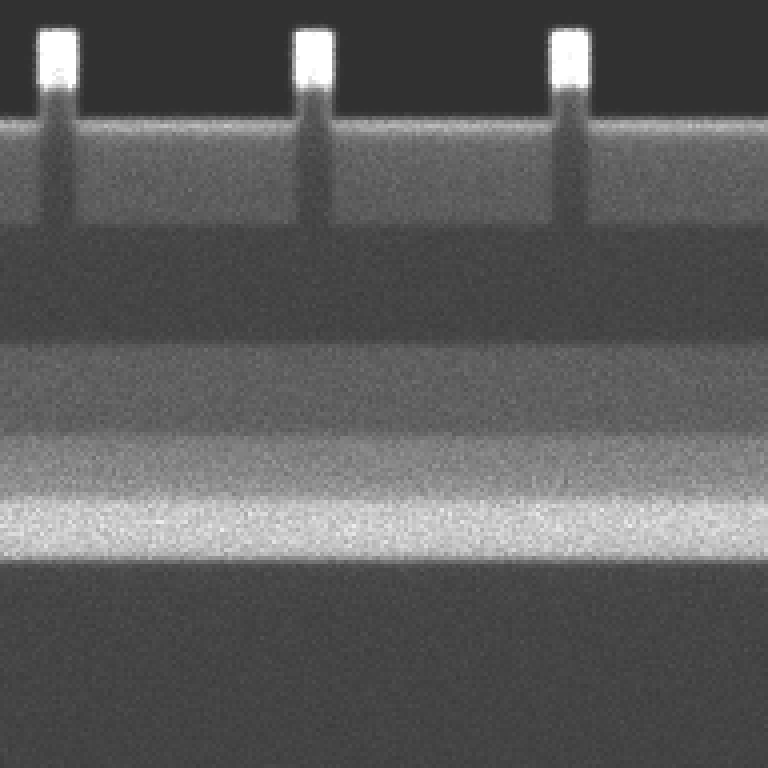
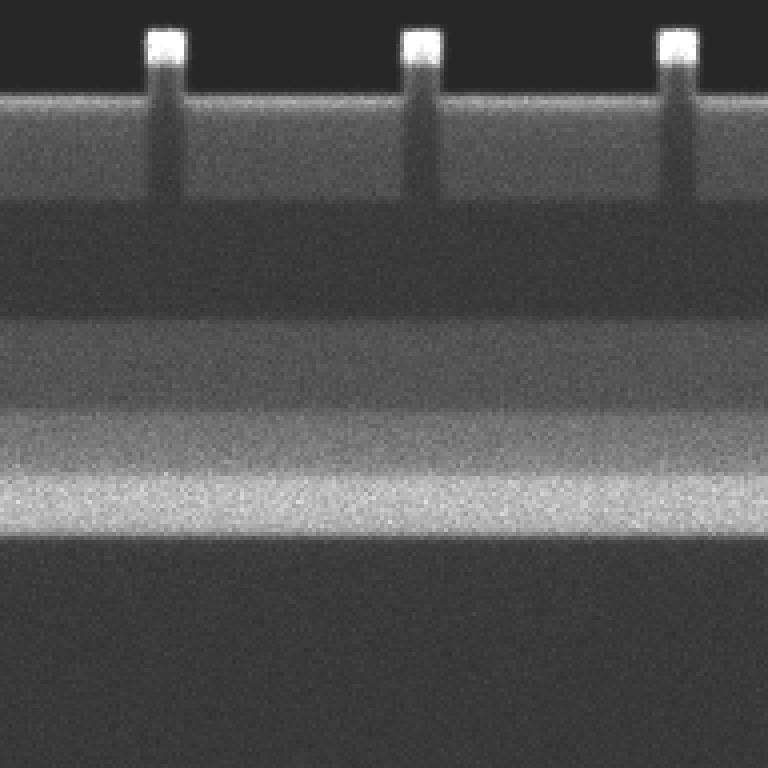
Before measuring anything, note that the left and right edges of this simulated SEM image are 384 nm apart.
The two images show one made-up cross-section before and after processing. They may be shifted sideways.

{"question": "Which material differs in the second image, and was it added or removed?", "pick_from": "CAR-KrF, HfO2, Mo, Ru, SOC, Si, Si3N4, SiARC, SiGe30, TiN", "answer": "HfO2, removed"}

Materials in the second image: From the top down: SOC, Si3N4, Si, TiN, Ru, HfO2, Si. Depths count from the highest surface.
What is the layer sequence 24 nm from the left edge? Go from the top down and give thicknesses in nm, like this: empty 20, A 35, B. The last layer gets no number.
empty 32, SOC 16, Si3N4 36, Si 60, TiN 46, Ru 32, HfO2 30, Si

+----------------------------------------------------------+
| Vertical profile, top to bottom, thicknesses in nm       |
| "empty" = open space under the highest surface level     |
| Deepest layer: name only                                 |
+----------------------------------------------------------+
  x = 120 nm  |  empty 32, SOC 16, Si3N4 36, Si 60, TiN 46, Ru 32, HfO2 30, Si